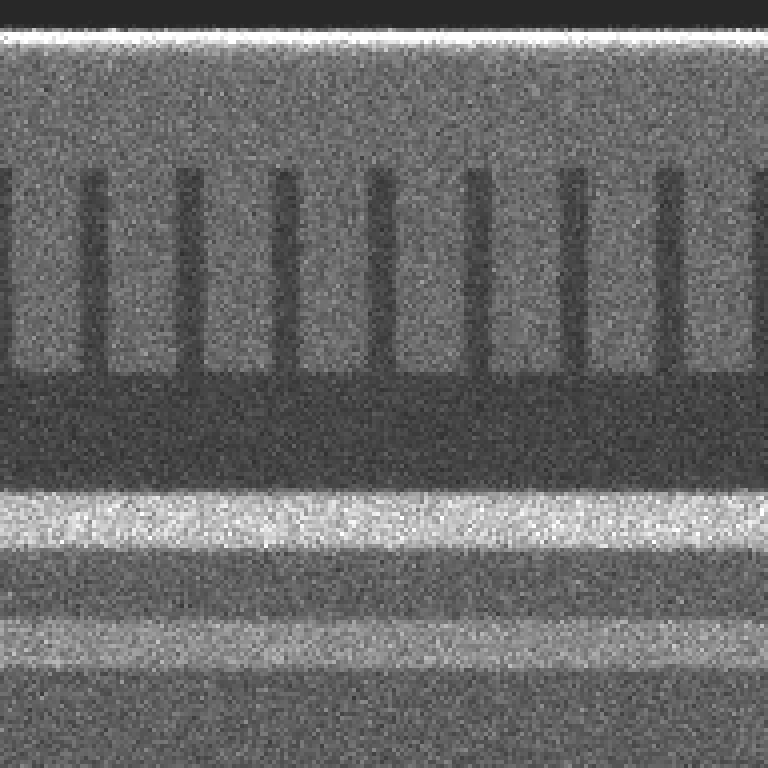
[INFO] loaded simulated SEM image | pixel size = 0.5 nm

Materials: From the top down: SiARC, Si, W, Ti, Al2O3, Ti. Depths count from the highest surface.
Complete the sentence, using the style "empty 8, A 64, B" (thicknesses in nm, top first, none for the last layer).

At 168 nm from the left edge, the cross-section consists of SiARC 170, Si 60, W 28, Ti 36, Al2O3 24, Ti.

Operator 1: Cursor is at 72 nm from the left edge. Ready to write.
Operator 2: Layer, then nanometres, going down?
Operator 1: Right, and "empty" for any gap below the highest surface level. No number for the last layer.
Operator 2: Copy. SiARC 170, Si 60, W 28, Ti 36, Al2O3 24, Ti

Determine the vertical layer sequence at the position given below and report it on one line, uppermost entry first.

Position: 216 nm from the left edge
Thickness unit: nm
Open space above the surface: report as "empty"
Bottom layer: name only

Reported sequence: SiARC 170, Si 60, W 28, Ti 36, Al2O3 24, Ti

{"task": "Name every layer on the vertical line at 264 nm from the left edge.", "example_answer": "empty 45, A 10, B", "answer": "SiARC 170, Si 60, W 28, Ti 36, Al2O3 24, Ti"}